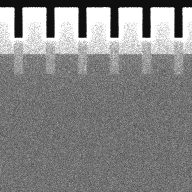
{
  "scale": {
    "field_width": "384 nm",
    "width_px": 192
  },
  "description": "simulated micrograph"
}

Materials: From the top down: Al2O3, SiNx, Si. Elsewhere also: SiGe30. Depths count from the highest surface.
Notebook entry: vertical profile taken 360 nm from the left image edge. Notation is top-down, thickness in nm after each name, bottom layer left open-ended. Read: empty 60, SiGe30 72, Si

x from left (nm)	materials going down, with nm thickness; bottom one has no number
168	empty 60, SiGe30 72, Si